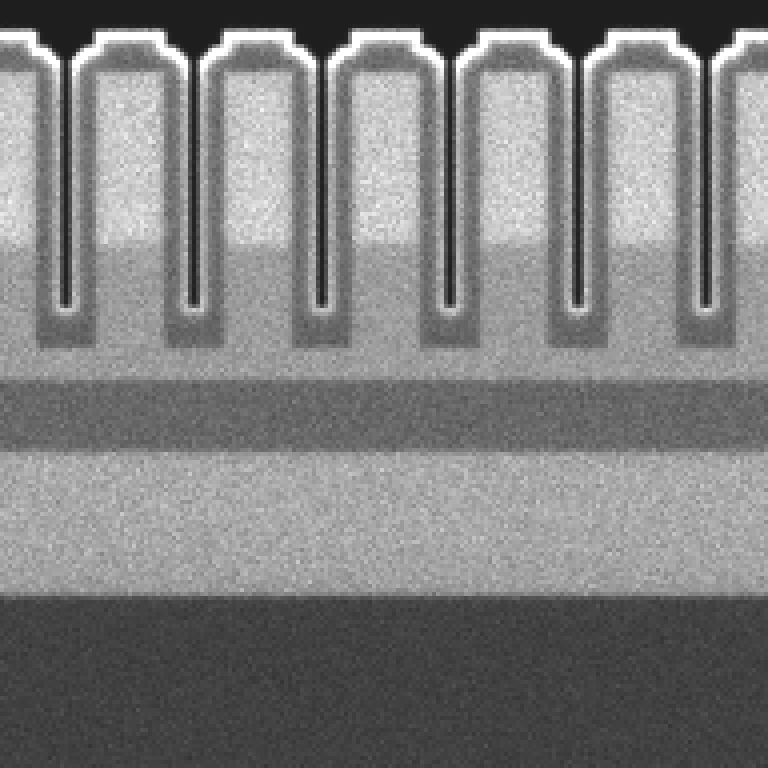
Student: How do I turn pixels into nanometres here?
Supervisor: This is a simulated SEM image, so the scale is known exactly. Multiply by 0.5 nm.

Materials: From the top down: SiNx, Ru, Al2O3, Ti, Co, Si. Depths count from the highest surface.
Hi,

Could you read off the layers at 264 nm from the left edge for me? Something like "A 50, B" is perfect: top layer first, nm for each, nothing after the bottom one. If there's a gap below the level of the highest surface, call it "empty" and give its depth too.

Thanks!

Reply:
SiNx 20, Ru 86, Al2O3 68, Ti 36, Co 72, Si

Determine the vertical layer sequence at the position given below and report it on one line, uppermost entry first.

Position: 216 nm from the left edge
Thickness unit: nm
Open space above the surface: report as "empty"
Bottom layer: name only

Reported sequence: empty 10, SiNx 148, Al2O3 16, Ti 36, Co 72, Si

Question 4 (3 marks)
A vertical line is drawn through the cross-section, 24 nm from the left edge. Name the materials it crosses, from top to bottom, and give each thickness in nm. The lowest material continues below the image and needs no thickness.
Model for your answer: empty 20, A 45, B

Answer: empty 10, SiNx 148, Al2O3 16, Ti 36, Co 72, Si